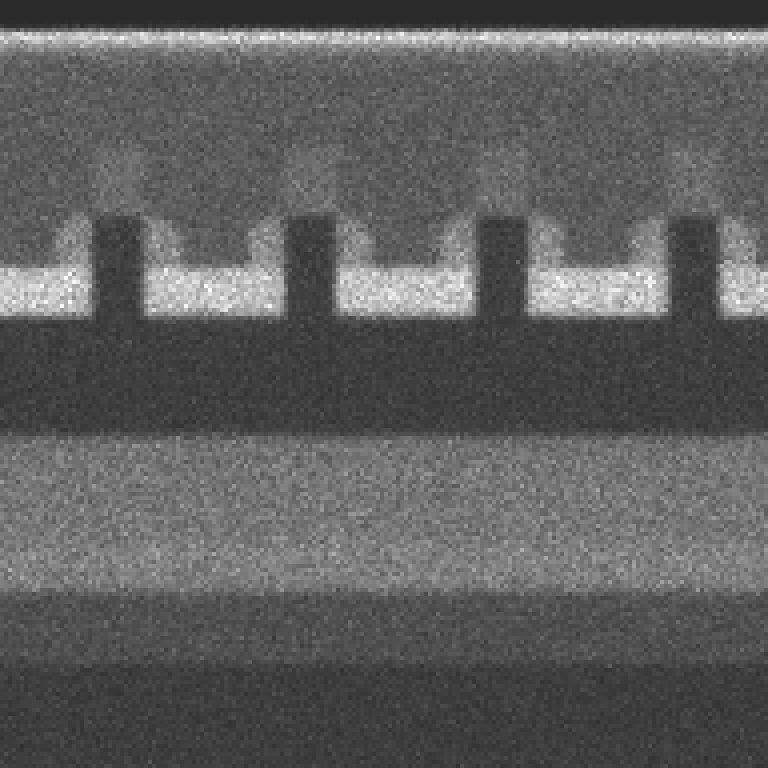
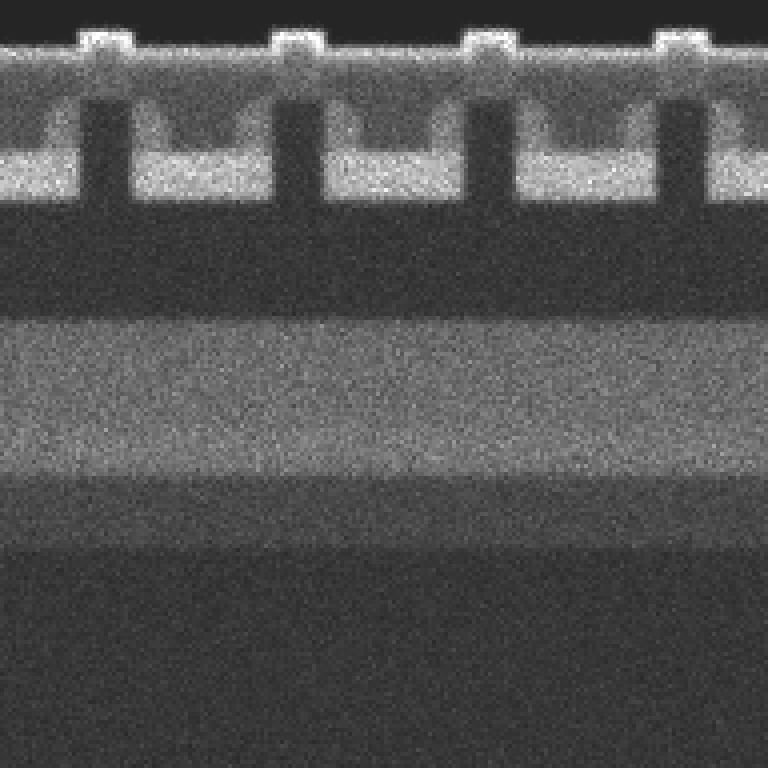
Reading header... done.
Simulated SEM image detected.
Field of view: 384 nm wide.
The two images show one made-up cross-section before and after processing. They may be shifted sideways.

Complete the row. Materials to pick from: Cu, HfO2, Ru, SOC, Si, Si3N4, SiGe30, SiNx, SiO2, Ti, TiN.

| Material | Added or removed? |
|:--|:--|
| SOC | removed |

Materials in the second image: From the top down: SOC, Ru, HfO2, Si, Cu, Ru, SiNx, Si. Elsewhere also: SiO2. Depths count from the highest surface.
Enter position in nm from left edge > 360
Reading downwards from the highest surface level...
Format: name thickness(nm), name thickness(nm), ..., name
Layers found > empty 8, SOC 26, Ru 26, HfO2 24, Si 60, Cu 54, Ru 24, SiNx 36, Si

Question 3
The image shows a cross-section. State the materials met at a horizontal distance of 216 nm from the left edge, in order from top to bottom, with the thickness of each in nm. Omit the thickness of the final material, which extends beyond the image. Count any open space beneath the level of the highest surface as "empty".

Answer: empty 8, SOC 32, Ru 20, HfO2 24, Si 60, Cu 54, Ru 24, SiNx 36, Si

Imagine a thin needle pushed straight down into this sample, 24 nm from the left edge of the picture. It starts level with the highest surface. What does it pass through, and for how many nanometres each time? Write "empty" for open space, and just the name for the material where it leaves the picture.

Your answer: empty 8, SOC 32, Ru 20, HfO2 24, Si 60, Cu 54, Ru 24, SiNx 36, Si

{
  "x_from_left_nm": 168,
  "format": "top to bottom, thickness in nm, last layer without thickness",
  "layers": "empty 8, SOC 26, Ru 26, HfO2 24, Si 60, Cu 54, Ru 24, SiNx 36, Si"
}